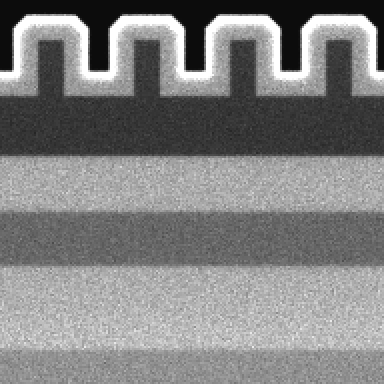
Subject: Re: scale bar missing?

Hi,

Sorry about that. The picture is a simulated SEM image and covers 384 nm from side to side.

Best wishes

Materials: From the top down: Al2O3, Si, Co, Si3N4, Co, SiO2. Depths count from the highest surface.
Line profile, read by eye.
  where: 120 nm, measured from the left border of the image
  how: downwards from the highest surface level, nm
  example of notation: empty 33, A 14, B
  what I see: empty 2, Al2O3 78, Si 60, Co 56, Si3N4 54, Co 84, SiO2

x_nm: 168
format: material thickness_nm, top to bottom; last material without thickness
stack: Al2O3 80, Si 60, Co 56, Si3N4 54, Co 84, SiO2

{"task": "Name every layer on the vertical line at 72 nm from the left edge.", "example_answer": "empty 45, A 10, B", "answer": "Al2O3 80, Si 60, Co 56, Si3N4 54, Co 84, SiO2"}